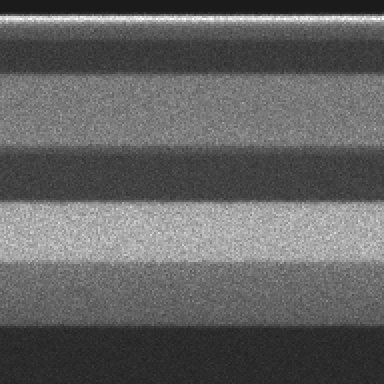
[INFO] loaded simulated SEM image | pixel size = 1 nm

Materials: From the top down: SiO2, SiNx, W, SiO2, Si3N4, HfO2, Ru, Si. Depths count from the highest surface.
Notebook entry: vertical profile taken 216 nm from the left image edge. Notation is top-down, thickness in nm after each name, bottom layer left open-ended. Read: SiO2 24, SiNx 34, W 72, SiO2 8, Si3N4 48, HfO2 60, Ru 64, Si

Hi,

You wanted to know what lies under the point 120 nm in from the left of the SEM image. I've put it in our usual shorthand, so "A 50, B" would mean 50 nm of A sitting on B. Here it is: SiO2 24, SiNx 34, W 72, SiO2 8, Si3N4 48, HfO2 60, Ru 64, Si